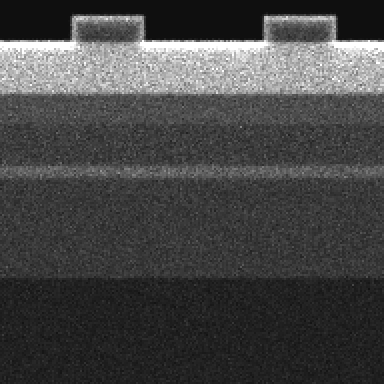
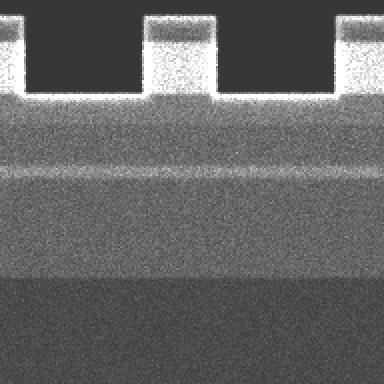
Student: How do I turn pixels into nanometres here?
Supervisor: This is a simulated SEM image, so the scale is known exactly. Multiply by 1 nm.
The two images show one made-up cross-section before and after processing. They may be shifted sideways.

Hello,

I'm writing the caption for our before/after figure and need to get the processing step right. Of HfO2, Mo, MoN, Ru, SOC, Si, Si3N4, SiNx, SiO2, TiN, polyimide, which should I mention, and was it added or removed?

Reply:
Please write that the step removed HfO2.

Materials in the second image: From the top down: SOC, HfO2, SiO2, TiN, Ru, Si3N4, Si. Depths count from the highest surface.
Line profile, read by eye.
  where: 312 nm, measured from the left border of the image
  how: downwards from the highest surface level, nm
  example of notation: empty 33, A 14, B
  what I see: empty 78, SiO2 30, TiN 42, Ru 12, Si3N4 100, Si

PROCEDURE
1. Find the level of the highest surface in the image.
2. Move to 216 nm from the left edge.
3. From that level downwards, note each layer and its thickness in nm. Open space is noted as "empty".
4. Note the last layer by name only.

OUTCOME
empty 78, SiO2 30, TiN 42, Ru 12, Si3N4 100, Si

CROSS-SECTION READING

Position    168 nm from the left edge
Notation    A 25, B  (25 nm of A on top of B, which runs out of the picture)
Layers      SOC 26, HfO2 52, SiO2 30, TiN 42, Ru 12, Si3N4 100, Si